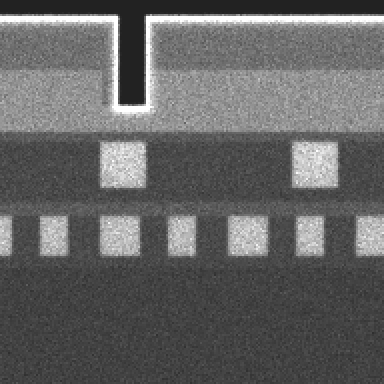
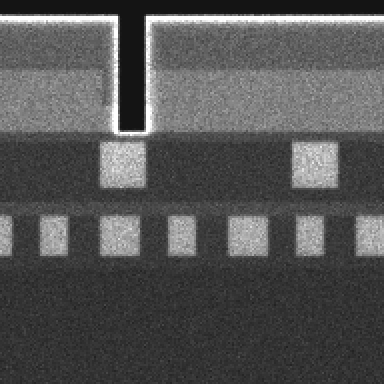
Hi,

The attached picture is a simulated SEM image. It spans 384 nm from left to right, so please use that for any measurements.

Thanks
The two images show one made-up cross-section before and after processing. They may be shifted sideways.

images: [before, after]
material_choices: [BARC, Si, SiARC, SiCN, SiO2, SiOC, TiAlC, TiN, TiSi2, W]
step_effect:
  removed: SiO2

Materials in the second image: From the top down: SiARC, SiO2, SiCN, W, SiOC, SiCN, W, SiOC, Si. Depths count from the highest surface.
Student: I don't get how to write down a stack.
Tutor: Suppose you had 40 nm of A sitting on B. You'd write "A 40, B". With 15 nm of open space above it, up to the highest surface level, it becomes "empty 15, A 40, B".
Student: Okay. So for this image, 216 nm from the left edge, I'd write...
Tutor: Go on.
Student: SiARC 54, SiO2 62, SiCN 10, SiOC 60, SiCN 14, SiOC 52, Si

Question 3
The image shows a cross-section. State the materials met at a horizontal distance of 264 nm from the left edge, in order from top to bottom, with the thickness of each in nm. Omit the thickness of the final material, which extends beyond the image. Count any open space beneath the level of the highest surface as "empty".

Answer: SiARC 54, SiO2 62, SiCN 10, SiOC 60, SiCN 14, W 40, SiOC 12, Si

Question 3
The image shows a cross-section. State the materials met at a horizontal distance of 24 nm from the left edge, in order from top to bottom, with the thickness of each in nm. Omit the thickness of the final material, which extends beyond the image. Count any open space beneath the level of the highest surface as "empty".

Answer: SiARC 54, SiO2 62, SiCN 10, SiOC 60, SiCN 14, SiOC 52, Si